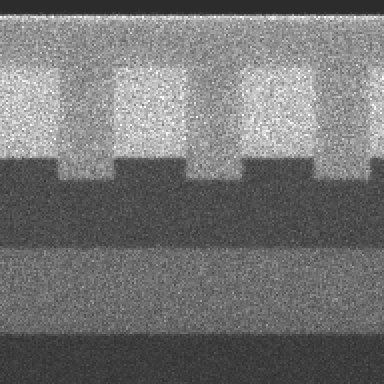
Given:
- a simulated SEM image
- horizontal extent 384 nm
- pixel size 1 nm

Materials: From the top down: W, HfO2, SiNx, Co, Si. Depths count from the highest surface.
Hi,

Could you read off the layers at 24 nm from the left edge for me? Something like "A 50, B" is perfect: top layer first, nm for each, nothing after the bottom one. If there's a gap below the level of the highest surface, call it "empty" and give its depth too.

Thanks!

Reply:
W 52, HfO2 90, SiNx 90, Co 86, Si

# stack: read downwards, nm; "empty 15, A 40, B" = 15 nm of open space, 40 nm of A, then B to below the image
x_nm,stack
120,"W 52, HfO2 90, SiNx 90, Co 86, Si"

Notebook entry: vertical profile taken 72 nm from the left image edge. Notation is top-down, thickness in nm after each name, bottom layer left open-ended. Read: W 164, SiNx 68, Co 86, Si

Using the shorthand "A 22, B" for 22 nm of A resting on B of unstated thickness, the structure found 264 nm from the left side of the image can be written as W 52, HfO2 90, SiNx 90, Co 86, Si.